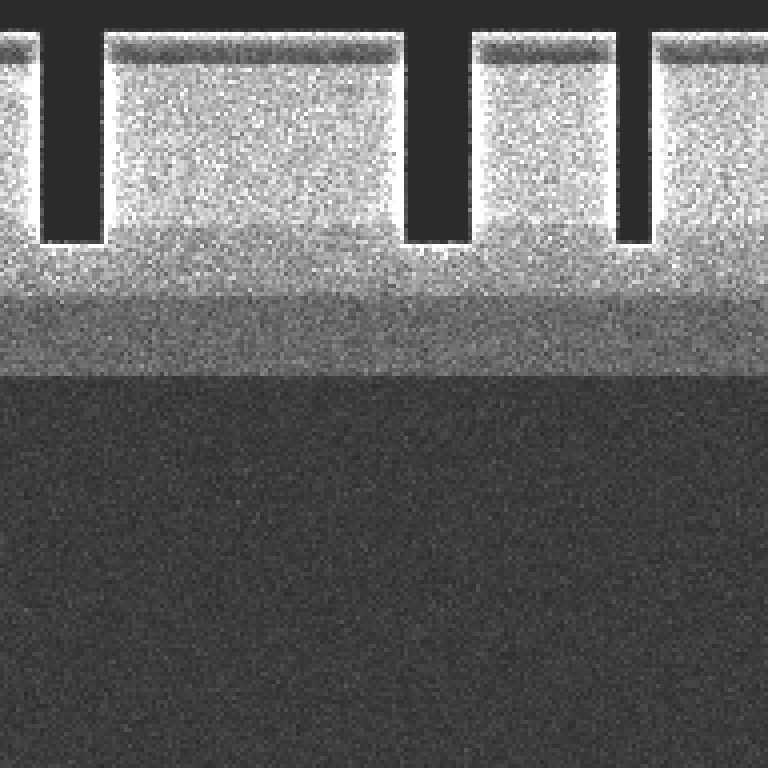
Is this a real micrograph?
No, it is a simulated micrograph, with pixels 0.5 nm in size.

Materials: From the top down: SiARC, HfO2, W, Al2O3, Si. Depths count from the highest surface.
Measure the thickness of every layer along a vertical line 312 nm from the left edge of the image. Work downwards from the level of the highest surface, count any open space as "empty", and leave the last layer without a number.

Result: empty 106, W 26, Al2O3 40, Si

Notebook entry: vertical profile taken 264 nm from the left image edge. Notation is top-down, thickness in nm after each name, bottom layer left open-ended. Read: SiARC 16, HfO2 80, W 36, Al2O3 40, Si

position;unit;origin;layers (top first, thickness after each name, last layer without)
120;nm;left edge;SiARC 16, HfO2 80, W 36, Al2O3 40, Si